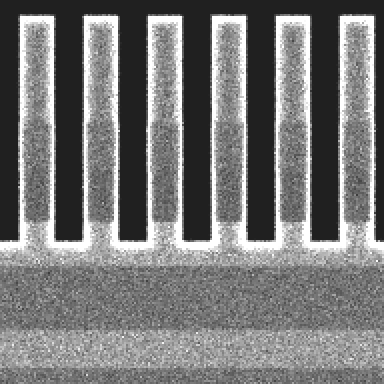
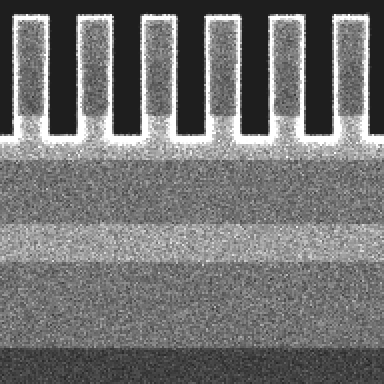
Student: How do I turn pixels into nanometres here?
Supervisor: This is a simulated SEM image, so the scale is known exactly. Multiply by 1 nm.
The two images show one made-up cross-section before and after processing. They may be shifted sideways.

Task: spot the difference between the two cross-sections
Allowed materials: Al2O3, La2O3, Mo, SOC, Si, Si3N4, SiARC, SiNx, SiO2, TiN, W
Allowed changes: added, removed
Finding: removed SOC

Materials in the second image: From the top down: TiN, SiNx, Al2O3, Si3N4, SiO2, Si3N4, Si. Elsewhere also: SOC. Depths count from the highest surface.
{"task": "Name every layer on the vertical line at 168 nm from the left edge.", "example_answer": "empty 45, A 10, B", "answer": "TiN 48, SiNx 52, Al2O3 44, Si3N4 64, SiO2 38, Si3N4 86, Si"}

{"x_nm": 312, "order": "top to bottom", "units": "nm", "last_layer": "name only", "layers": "empty 120, Al2O3 24, Si3N4 64, SiO2 38, Si3N4 86, Si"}